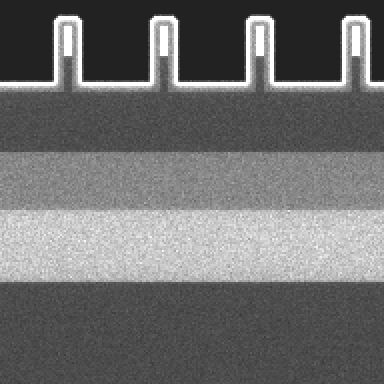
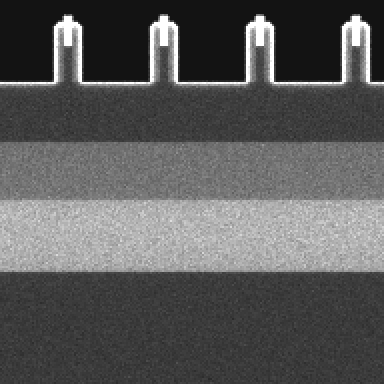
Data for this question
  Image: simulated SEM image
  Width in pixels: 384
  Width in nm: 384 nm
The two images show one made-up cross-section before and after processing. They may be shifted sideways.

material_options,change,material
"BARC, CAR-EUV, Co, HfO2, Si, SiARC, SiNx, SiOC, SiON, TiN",removed,SiNx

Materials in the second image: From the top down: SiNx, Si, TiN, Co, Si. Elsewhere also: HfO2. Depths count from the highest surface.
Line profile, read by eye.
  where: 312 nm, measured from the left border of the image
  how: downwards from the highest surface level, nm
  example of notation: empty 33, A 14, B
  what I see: empty 66, Si 60, TiN 58, Co 72, Si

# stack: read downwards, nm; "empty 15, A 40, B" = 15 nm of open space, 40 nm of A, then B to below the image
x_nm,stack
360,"empty 6, SiNx 60, Si 60, TiN 58, Co 72, Si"